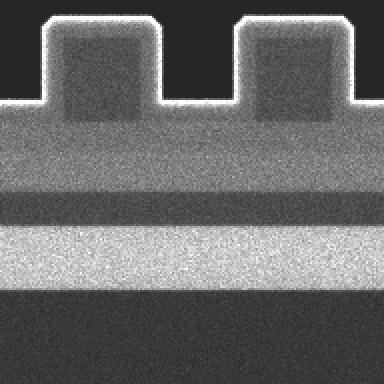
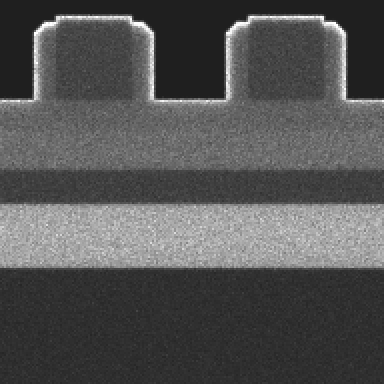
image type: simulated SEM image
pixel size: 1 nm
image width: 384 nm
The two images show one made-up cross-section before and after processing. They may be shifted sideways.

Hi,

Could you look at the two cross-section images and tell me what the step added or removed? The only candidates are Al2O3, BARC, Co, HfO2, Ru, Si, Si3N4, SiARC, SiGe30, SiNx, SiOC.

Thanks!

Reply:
removed Al2O3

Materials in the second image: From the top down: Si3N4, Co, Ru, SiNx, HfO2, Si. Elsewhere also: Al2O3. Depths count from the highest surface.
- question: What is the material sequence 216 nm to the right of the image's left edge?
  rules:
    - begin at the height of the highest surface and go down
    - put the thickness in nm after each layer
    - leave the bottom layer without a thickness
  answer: empty 84, Co 30, Ru 40, SiNx 34, HfO2 64, Si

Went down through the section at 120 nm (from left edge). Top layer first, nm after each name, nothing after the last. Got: Si3N4 84, Co 30, Ru 40, SiNx 34, HfO2 64, Si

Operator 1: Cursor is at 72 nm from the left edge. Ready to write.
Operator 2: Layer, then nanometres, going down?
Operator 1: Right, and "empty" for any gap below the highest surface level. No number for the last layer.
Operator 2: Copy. Si3N4 84, Co 30, Ru 40, SiNx 34, HfO2 64, Si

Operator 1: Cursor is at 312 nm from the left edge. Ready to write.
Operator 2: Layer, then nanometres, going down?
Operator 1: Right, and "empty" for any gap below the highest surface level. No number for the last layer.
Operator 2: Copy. Si3N4 84, Co 30, Ru 40, SiNx 34, HfO2 64, Si